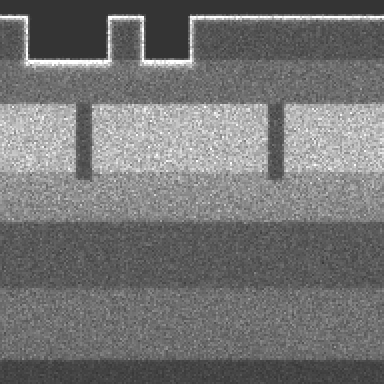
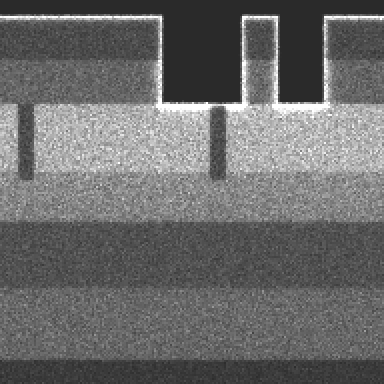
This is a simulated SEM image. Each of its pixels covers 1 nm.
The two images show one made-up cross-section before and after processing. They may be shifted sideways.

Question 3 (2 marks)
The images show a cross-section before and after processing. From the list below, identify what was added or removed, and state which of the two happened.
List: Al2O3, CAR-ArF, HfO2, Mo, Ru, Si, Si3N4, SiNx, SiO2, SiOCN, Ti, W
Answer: SiO2 was removed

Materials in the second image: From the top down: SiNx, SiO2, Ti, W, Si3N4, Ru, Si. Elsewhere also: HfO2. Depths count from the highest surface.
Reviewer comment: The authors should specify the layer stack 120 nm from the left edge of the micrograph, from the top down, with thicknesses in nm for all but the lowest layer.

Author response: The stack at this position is SiNx 44, SiO2 44, HfO2 68, W 50, Si3N4 66, Ru 72, Si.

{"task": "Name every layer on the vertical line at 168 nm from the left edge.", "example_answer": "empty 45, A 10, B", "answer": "empty 88, HfO2 68, W 50, Si3N4 66, Ru 72, Si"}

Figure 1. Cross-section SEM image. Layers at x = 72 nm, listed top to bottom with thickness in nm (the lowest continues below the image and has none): SiNx 44, SiO2 44, HfO2 68, W 50, Si3N4 66, Ru 72, Si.